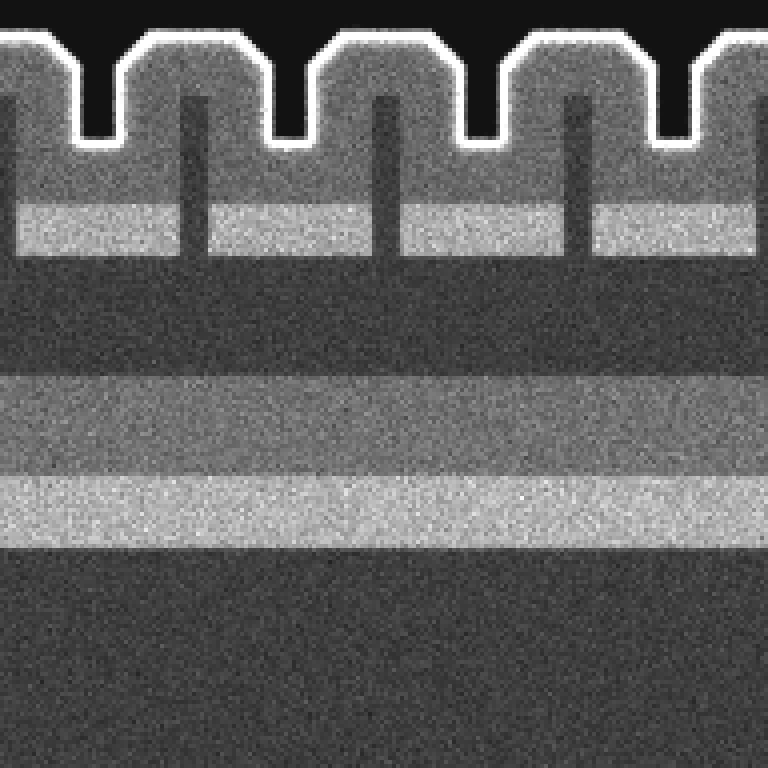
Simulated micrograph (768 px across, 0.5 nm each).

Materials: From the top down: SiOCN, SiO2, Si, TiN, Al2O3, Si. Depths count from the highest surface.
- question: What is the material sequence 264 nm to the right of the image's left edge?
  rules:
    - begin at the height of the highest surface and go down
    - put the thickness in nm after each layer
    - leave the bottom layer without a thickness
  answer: empty 2, SiOCN 84, SiO2 26, Si 60, TiN 50, Al2O3 36, Si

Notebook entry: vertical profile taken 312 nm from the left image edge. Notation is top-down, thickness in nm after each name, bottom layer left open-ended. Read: empty 2, SiOCN 84, SiO2 26, Si 60, TiN 50, Al2O3 36, Si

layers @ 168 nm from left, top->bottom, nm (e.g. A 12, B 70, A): empty 2, SiOCN 84, SiO2 26, Si 60, TiN 50, Al2O3 36, Si